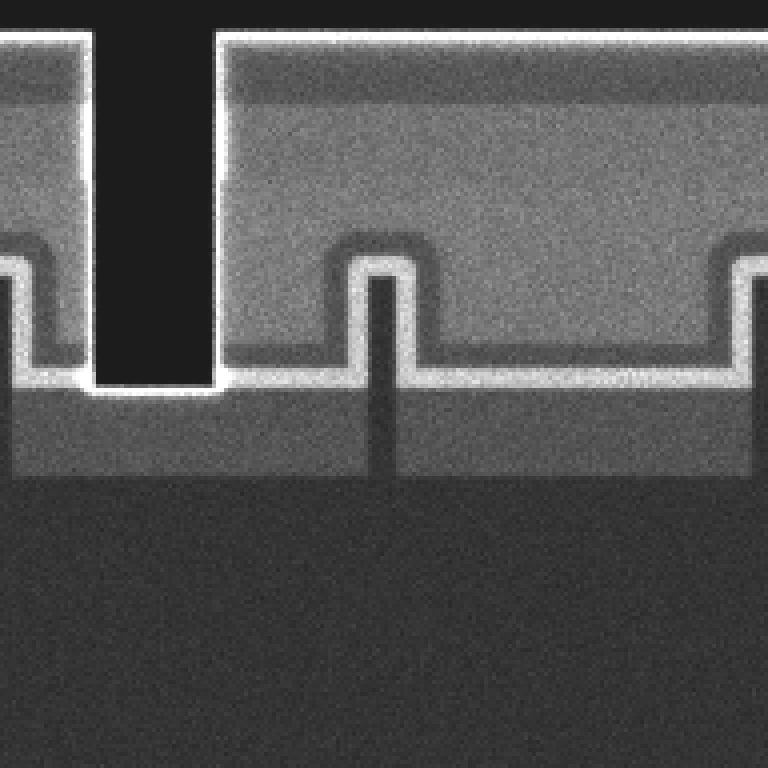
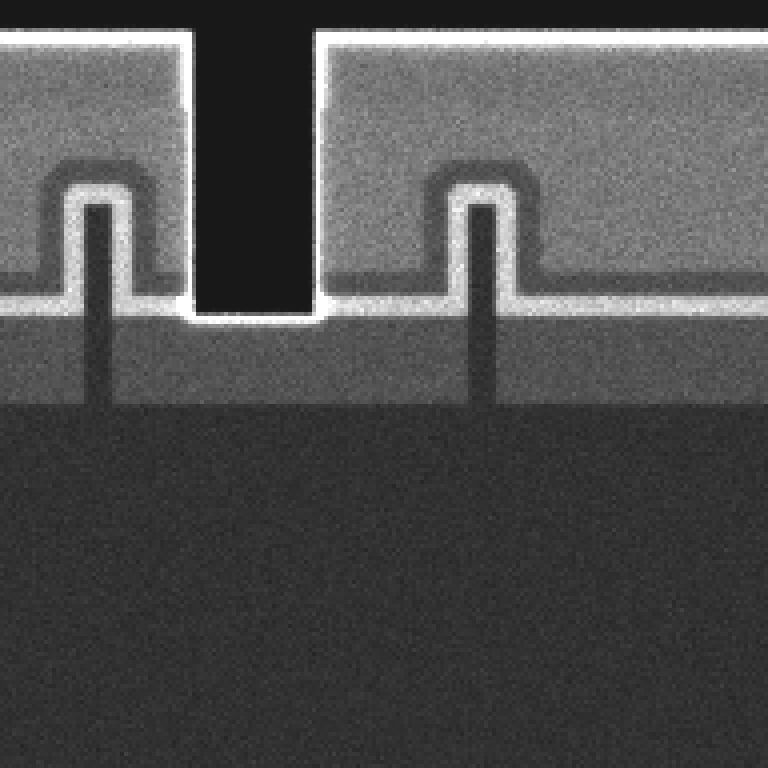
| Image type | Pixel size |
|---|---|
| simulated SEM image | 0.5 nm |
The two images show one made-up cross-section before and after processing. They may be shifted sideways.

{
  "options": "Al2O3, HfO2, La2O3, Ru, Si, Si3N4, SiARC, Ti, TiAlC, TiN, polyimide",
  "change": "removed",
  "material": "SiARC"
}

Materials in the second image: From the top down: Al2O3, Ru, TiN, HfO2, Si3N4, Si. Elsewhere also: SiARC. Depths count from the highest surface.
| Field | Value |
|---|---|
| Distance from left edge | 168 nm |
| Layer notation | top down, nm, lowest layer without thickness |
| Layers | Al2O3 38, Ru 82, TiN 12, HfO2 10, Si3N4 44, Si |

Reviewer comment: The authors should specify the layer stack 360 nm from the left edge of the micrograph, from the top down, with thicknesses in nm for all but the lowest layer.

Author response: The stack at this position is Al2O3 38, Ru 82, TiN 12, HfO2 10, Si3N4 44, Si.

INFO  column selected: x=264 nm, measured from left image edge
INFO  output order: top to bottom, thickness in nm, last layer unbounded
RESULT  Al2O3 38, Ru 32, TiN 62, HfO2 10, Si3N4 44, Si